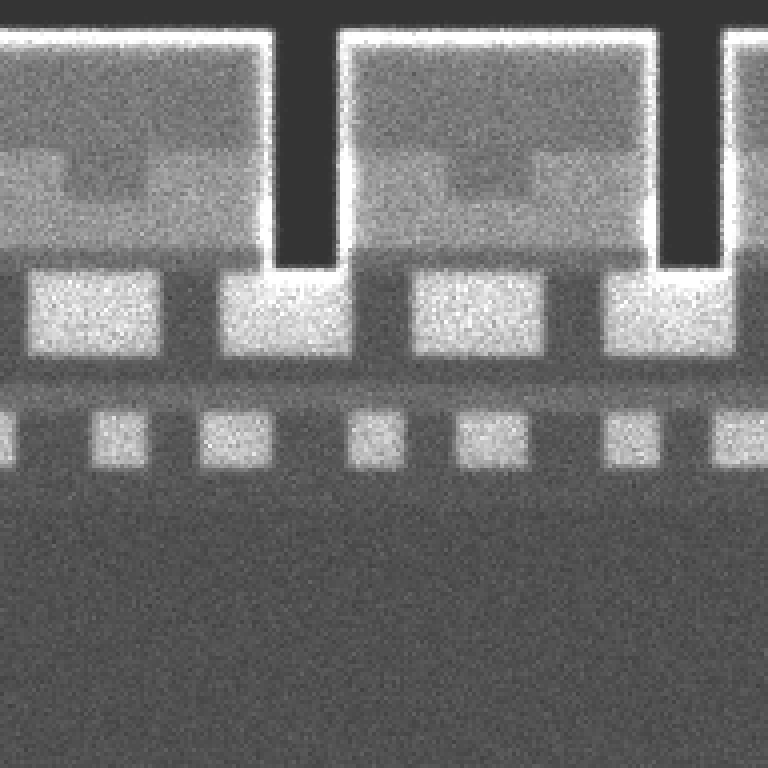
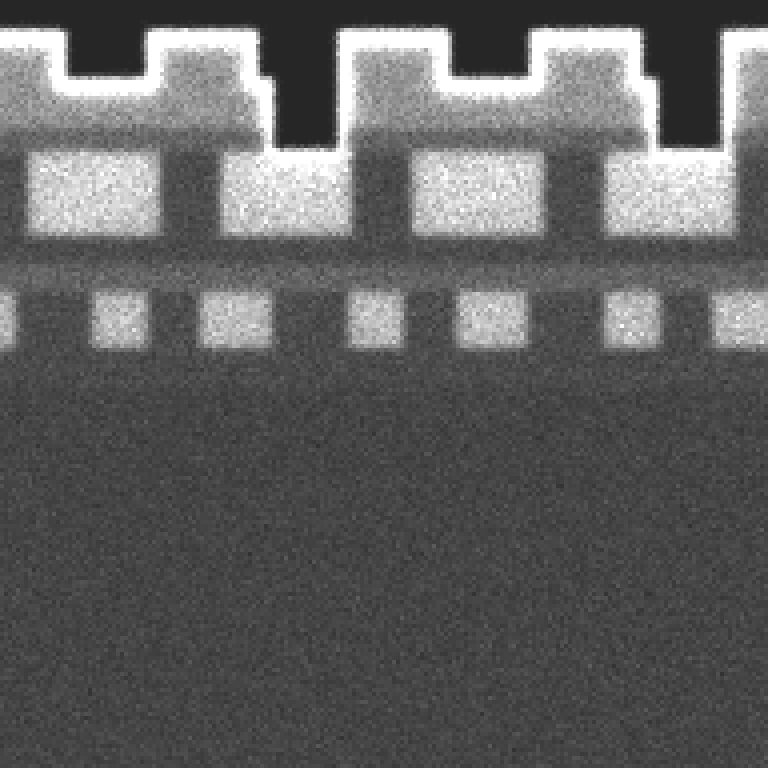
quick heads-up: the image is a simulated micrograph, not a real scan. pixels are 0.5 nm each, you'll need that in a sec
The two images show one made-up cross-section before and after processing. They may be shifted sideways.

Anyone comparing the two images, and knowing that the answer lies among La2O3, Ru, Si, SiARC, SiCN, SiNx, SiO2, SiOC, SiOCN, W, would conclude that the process removed SiARC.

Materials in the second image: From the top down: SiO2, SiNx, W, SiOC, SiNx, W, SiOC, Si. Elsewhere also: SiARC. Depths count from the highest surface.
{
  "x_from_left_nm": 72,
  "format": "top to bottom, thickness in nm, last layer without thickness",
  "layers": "empty 24, SiO2 24, SiNx 12, W 42, SiOC 14, SiNx 14, W 28, SiOC 20, Si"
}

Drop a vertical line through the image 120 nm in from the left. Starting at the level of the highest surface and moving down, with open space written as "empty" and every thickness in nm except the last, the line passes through SiO2 48, SiNx 12, W 42, SiOC 14, SiNx 14, W 28, SiOC 20, Si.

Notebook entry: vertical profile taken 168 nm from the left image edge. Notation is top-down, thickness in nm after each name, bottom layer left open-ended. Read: empty 60, W 42, SiOC 14, SiNx 14, SiOC 48, Si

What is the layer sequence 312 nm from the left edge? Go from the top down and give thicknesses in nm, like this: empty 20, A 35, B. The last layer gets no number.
SiO2 48, SiNx 12, W 42, SiOC 14, SiNx 14, W 28, SiOC 20, Si